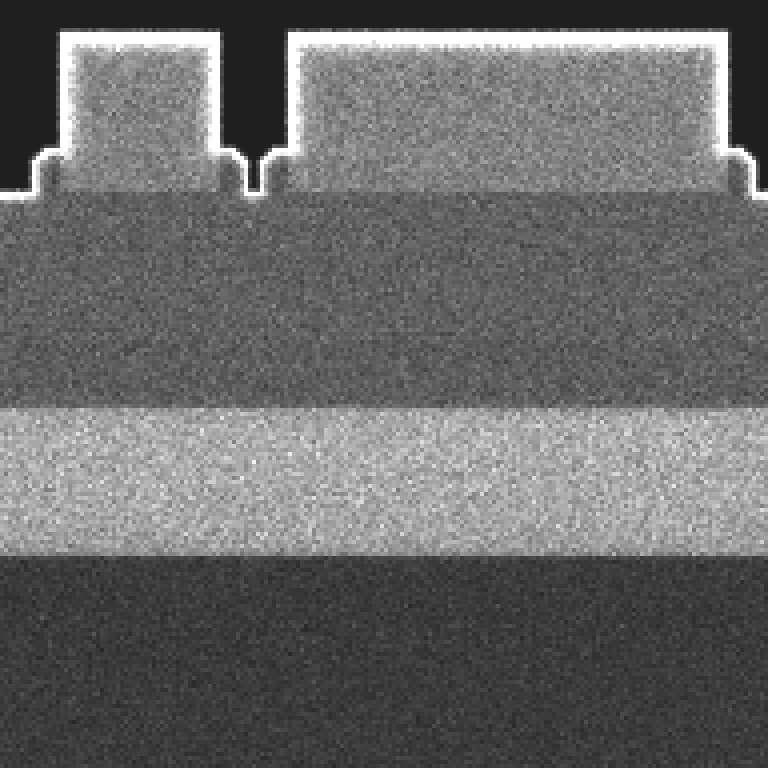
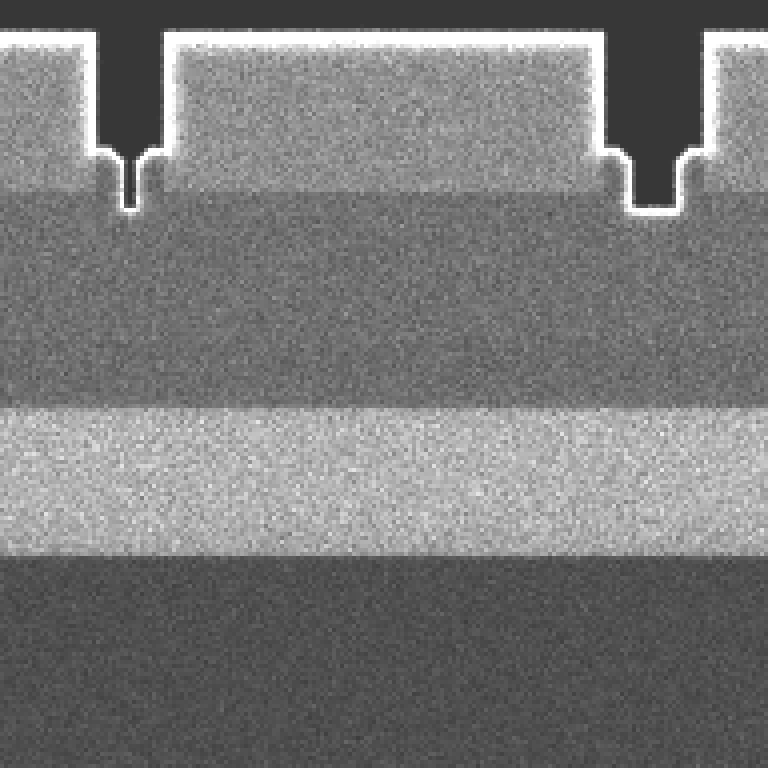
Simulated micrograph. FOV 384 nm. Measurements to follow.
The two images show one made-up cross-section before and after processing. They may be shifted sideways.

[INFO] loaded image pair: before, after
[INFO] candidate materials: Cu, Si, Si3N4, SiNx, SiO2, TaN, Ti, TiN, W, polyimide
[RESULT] removed Si3N4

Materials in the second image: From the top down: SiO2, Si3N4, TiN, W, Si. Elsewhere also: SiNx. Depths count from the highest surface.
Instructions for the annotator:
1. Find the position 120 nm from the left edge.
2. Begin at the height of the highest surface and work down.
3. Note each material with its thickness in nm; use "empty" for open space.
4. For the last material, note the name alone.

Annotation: SiO2 80, Si3N4 74, TiN 34, W 74, Si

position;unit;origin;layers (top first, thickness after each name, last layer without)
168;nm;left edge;SiO2 80, Si3N4 74, TiN 34, W 74, Si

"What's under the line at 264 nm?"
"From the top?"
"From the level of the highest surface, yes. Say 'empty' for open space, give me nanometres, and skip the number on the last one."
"SiO2 80, Si3N4 74, TiN 34, W 74, Si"